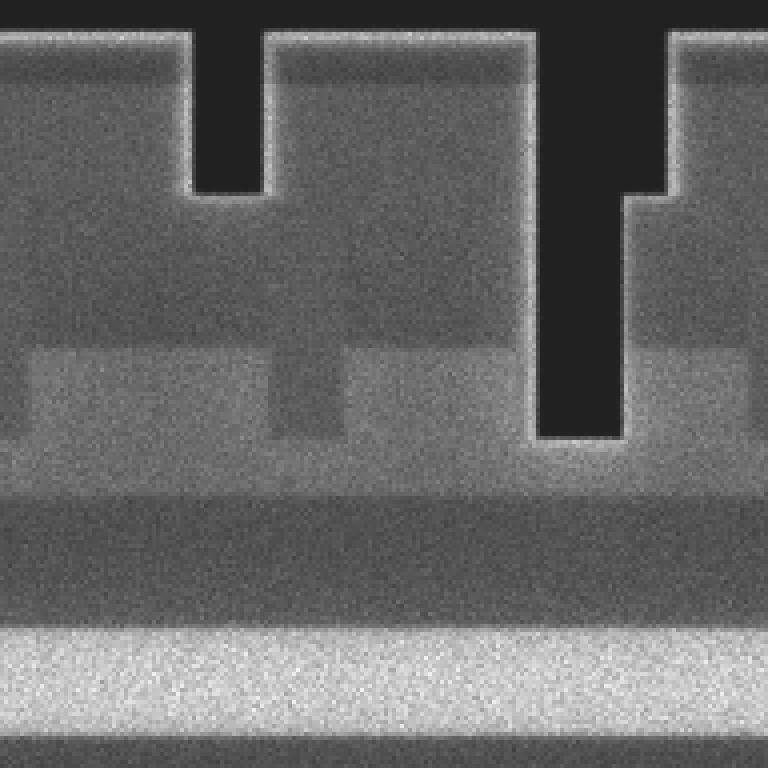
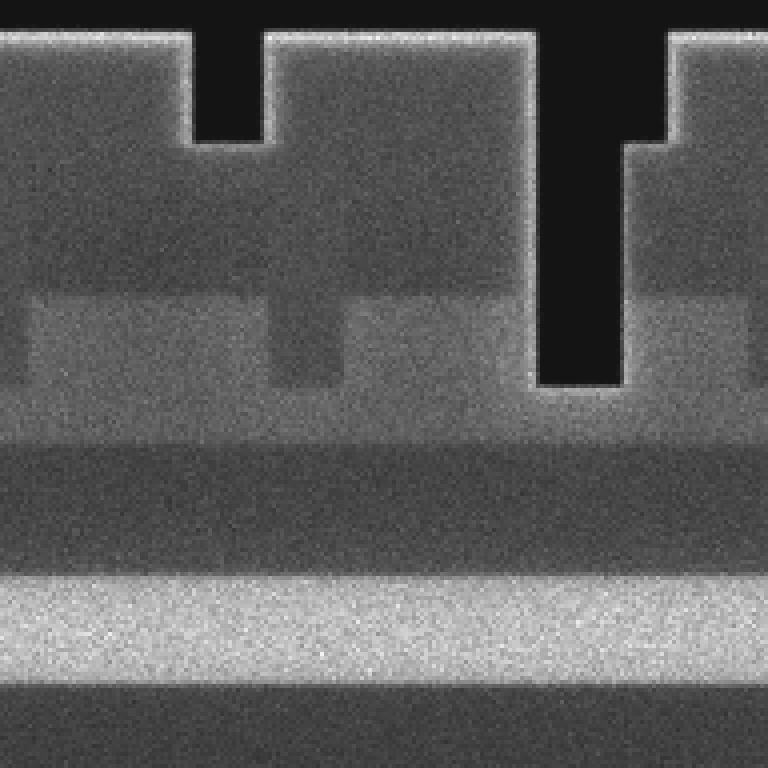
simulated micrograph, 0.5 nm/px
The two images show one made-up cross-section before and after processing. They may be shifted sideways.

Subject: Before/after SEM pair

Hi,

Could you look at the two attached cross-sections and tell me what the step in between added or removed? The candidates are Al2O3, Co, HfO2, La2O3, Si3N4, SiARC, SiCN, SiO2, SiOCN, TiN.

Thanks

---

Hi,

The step removed SiARC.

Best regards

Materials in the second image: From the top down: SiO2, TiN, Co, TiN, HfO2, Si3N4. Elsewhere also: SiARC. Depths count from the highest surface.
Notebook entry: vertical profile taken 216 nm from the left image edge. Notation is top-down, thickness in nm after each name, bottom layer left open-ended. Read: SiO2 56, TiN 76, Co 74, TiN 66, HfO2 54, Si3N4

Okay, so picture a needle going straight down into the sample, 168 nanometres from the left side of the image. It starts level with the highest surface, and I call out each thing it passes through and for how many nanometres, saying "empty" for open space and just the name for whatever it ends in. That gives SiO2 178, Co 28, TiN 66, HfO2 54, Si3N4